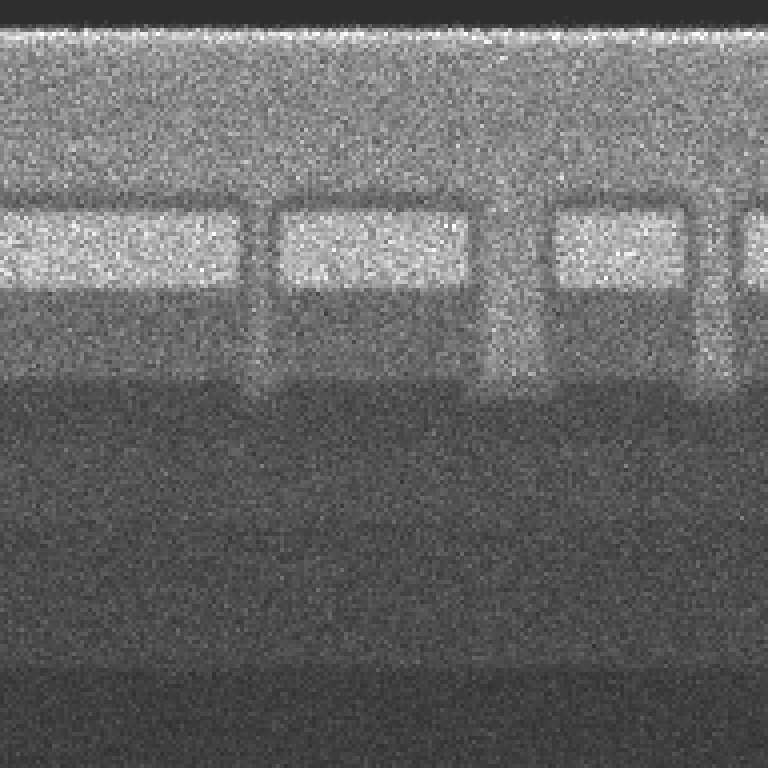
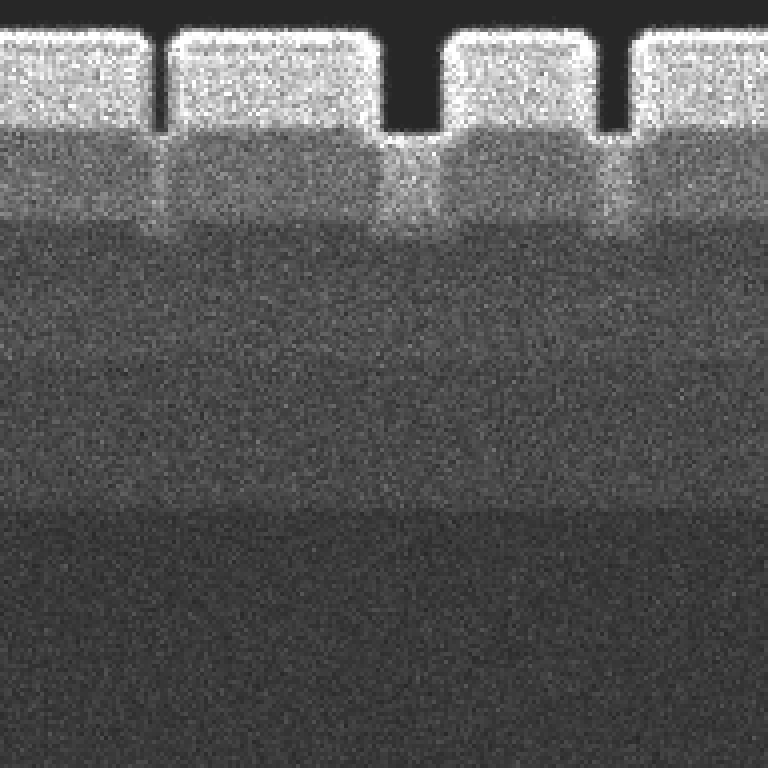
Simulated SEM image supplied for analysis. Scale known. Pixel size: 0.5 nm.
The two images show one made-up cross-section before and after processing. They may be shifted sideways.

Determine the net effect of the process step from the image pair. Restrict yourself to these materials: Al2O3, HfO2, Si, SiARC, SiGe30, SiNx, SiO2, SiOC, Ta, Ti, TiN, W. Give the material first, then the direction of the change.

W: removed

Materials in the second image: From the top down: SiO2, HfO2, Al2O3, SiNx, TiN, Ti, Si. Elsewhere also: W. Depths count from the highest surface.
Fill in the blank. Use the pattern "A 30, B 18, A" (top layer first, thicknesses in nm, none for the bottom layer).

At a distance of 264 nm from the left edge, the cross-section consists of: SiO2 10, HfO2 38, Al2O3 46, SiNx 32, TiN 38, Ti 74, Si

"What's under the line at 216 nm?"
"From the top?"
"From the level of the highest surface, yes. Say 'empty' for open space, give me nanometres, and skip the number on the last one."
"empty 52, W 42, SiO2 10, SiNx 22, TiN 38, Ti 74, Si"